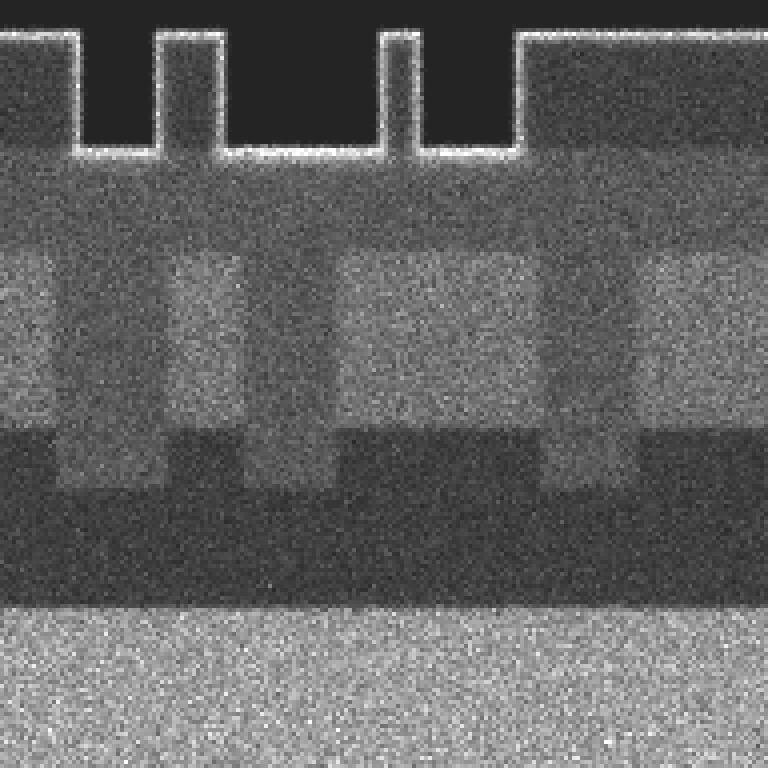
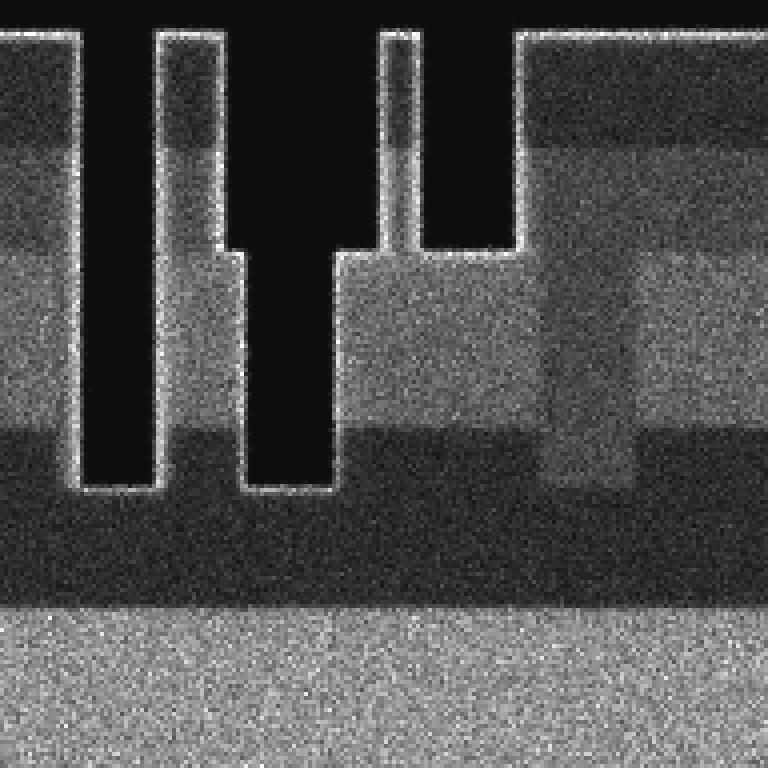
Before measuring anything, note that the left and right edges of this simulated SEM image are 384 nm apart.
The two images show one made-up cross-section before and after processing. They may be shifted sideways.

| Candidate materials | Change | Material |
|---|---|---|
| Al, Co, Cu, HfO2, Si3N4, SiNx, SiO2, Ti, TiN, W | removed | SiO2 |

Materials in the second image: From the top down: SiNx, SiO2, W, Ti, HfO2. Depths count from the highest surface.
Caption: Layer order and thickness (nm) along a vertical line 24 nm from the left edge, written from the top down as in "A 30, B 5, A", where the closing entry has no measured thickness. SiNx 58, SiO2 52, W 88, Ti 90, HfO2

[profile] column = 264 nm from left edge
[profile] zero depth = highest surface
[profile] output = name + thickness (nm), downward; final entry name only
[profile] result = SiNx 58, SiO2 52, W 88, Ti 90, HfO2